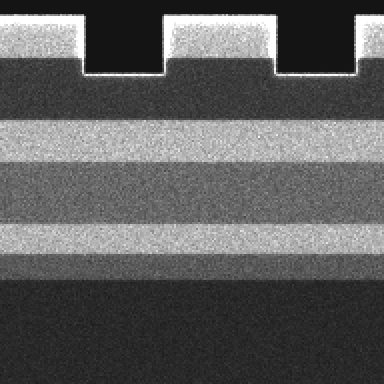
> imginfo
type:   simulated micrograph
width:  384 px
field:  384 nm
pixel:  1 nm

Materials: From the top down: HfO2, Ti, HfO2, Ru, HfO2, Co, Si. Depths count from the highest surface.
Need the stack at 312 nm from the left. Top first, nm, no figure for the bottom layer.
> empty 58, Ti 46, HfO2 42, Ru 62, HfO2 30, Co 26, Si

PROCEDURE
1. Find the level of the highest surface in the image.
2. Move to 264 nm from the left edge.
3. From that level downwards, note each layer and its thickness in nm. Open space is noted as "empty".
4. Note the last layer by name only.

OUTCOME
HfO2 42, Ti 62, HfO2 42, Ru 62, HfO2 30, Co 26, Si